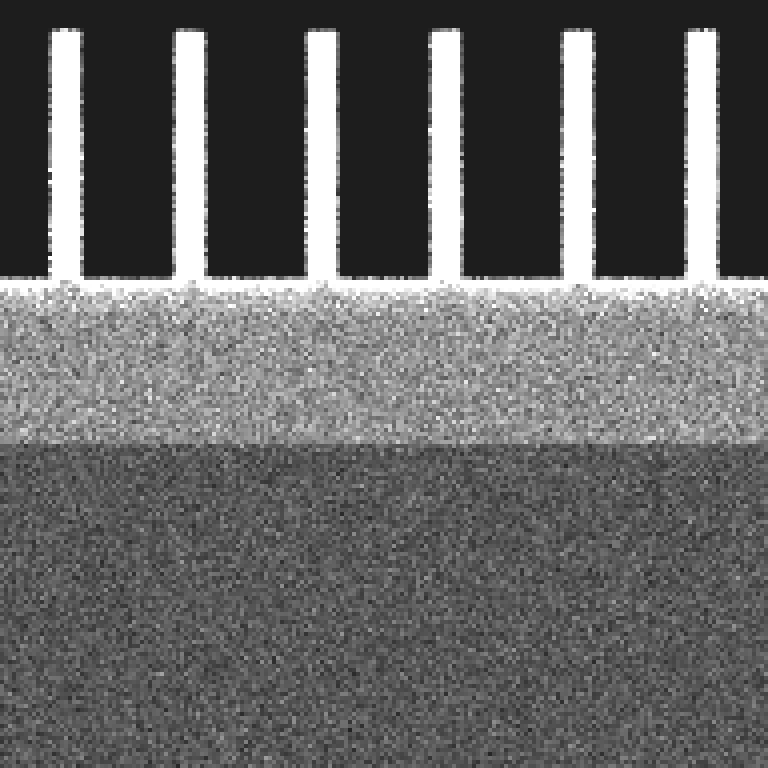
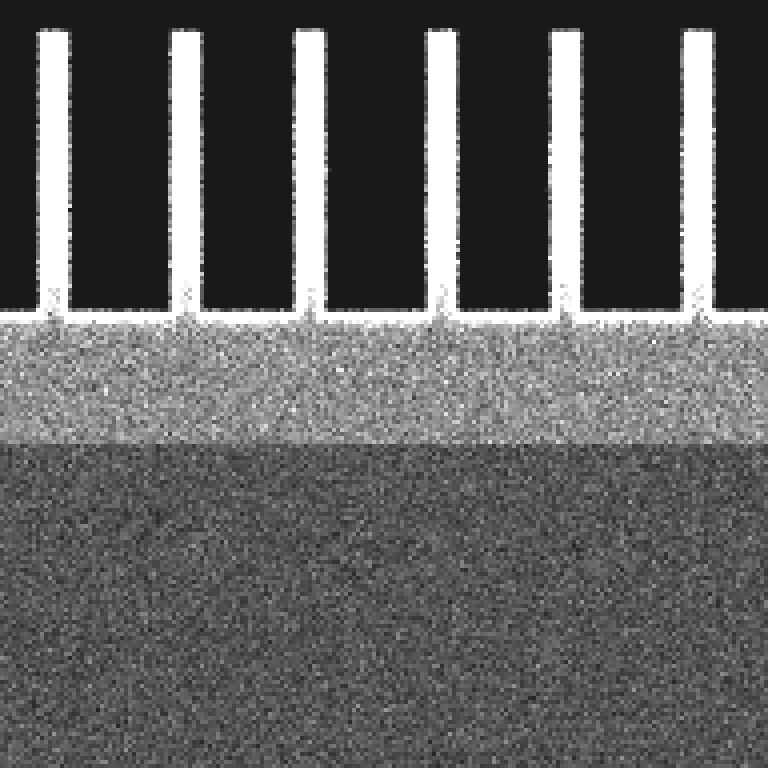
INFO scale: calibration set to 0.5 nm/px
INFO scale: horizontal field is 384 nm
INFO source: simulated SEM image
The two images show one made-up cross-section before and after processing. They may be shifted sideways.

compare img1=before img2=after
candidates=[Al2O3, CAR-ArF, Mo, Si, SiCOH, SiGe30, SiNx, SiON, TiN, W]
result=removed:TiN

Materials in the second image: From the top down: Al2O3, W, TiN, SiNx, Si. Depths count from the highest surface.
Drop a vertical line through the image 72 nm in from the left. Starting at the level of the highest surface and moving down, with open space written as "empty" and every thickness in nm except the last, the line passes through empty 140, SiNx 66, Si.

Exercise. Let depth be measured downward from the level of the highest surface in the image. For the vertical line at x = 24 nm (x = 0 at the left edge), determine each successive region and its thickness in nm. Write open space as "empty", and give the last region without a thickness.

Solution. Al2O3 48, W 76, TiN 16, SiNx 66, Si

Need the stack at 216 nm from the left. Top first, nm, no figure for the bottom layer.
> Al2O3 48, W 76, TiN 16, SiNx 66, Si